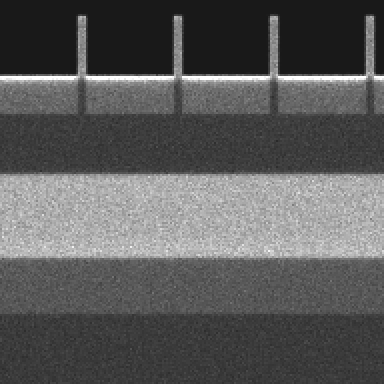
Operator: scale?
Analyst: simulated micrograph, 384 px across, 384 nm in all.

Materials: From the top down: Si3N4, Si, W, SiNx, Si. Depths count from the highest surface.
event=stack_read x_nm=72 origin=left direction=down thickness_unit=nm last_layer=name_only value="empty 60, Si3N4 38, Si 60, W 84, SiNx 56, Si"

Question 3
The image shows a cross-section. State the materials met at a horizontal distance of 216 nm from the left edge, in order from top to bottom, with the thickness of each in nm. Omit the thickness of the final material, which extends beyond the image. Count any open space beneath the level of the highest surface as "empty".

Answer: empty 60, Si3N4 38, Si 60, W 84, SiNx 56, Si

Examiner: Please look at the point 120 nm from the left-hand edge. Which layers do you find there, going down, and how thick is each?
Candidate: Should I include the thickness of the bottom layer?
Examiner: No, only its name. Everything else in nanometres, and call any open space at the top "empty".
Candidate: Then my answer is empty 60, Si3N4 38, Si 60, W 84, SiNx 56, Si